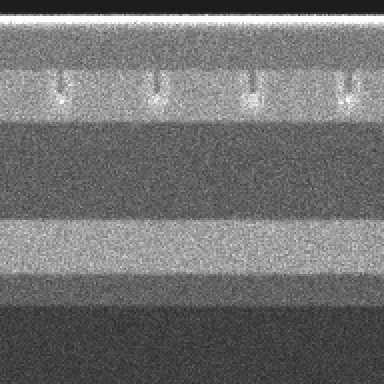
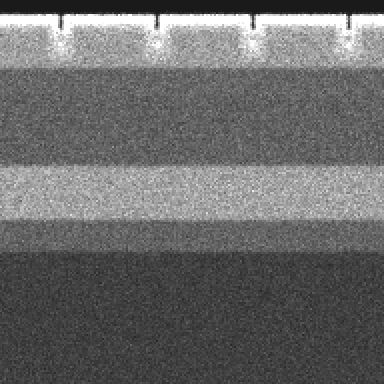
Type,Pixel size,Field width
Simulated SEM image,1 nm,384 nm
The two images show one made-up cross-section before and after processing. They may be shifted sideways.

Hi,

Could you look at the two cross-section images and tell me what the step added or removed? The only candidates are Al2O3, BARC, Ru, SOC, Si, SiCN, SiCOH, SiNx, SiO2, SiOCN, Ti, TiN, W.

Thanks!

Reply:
removed SOC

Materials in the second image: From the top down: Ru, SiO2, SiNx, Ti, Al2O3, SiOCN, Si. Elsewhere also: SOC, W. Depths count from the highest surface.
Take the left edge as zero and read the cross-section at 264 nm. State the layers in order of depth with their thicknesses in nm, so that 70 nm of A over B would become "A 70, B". Ru 44, SiO2 8, SiNx 28, Ti 70, Al2O3 54, SiOCN 32, Si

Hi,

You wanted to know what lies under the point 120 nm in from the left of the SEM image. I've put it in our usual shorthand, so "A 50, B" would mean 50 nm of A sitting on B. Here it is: SiO2 52, SiNx 28, Ti 70, Al2O3 54, SiOCN 32, Si